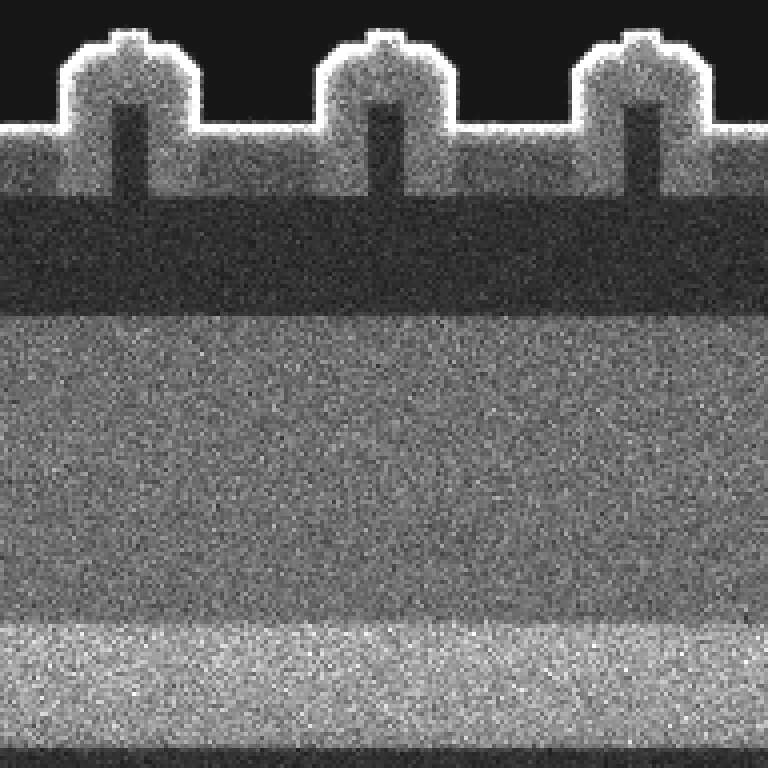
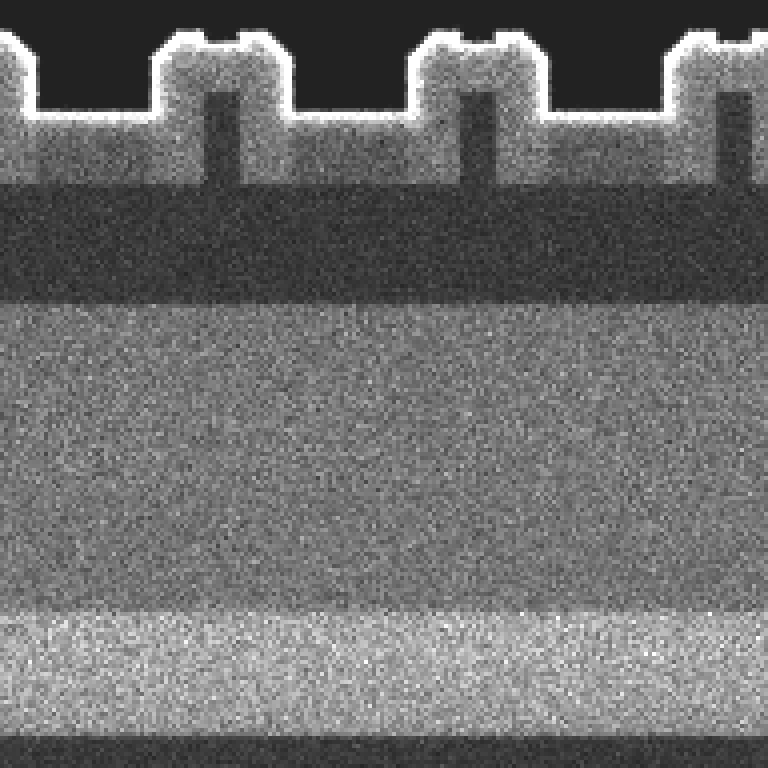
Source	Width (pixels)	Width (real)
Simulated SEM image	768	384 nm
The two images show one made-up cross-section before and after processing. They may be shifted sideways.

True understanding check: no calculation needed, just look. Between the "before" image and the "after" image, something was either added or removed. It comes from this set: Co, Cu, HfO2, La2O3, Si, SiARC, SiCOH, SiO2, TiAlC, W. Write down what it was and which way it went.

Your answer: Co (removed)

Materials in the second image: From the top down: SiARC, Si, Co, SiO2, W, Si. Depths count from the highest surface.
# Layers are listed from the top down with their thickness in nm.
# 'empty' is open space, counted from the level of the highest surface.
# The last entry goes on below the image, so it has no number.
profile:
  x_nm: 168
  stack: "empty 40, SiARC 36, Si 60, Co 90, SiO2 64, W 62, Si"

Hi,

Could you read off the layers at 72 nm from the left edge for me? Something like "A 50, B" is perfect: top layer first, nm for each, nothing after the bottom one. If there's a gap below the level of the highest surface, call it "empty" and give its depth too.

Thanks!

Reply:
empty 40, SiARC 36, Si 60, Co 90, SiO2 64, W 62, Si